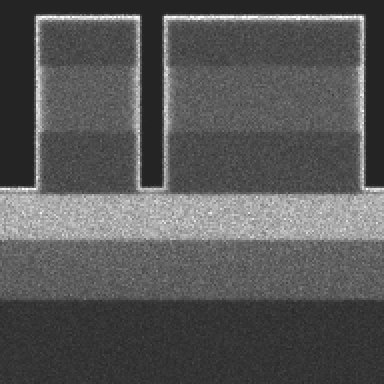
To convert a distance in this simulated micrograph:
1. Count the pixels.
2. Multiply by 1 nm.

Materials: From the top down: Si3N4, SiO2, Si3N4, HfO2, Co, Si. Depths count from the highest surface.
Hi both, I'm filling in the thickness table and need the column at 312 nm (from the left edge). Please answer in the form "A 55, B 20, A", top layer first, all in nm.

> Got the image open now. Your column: Si3N4 50, SiO2 66, Si3N4 62, HfO2 46, Co 60, Si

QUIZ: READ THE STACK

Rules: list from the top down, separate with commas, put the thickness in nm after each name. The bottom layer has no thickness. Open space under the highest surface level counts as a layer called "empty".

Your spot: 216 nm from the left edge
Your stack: Si3N4 50, SiO2 66, Si3N4 62, HfO2 46, Co 60, Si